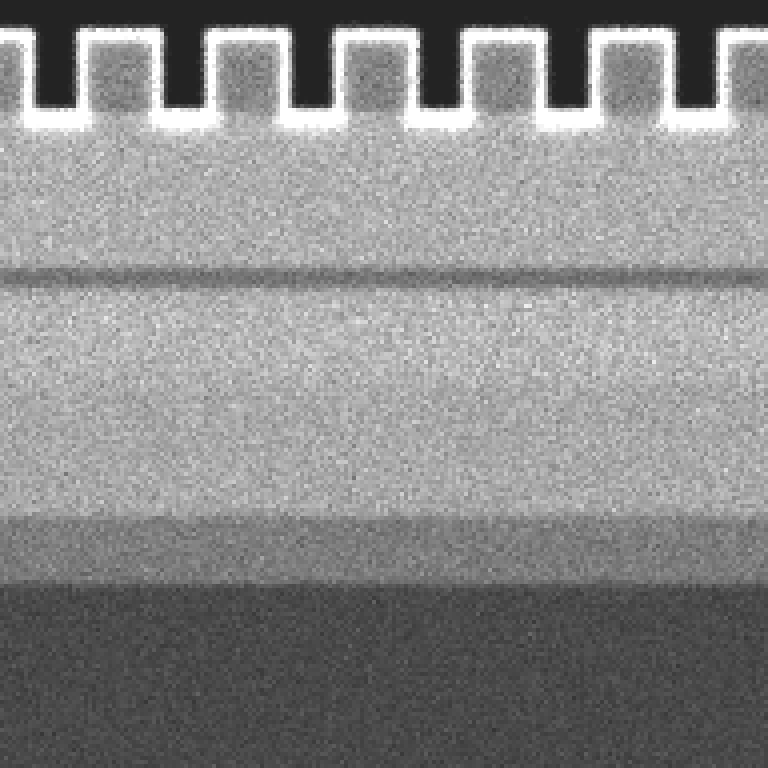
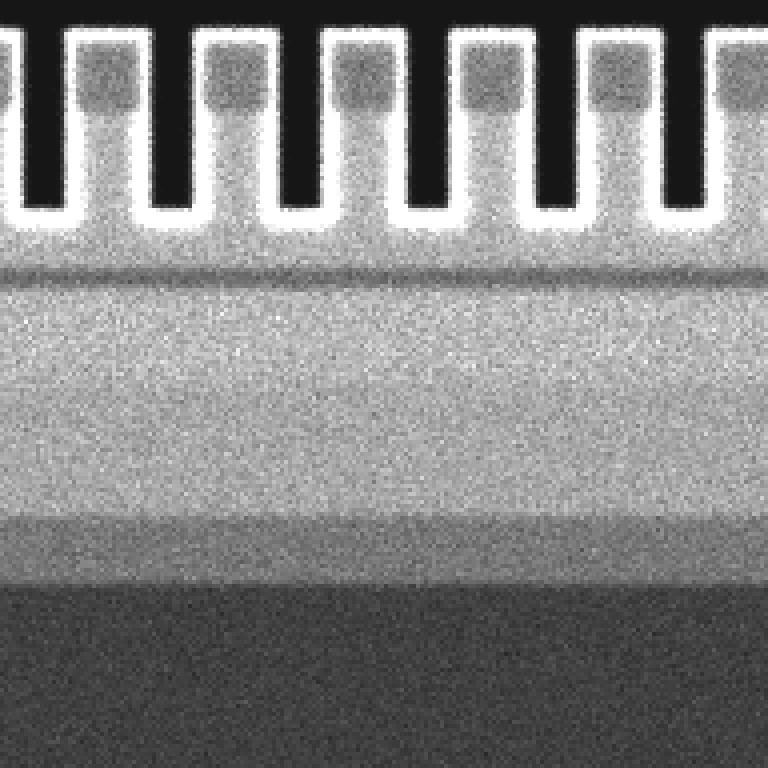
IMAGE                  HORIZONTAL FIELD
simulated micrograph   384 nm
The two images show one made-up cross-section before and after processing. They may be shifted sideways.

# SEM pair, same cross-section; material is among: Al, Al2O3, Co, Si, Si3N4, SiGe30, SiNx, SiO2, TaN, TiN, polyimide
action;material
removed;Al2O3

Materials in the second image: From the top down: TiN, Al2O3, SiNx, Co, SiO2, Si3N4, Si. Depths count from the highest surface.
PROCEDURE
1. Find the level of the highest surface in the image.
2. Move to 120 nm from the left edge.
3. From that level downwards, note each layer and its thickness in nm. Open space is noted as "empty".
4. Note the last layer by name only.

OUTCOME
TiN 40, Al2O3 78, SiNx 10, Co 48, SiO2 66, Si3N4 34, Si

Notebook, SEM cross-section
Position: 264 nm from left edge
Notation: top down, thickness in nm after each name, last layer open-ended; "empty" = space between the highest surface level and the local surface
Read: TiN 40, Al2O3 78, SiNx 10, Co 48, SiO2 66, Si3N4 34, Si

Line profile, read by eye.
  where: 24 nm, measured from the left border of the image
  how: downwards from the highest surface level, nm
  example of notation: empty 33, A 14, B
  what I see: empty 90, Al2O3 28, SiNx 10, Co 48, SiO2 66, Si3N4 34, Si